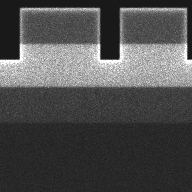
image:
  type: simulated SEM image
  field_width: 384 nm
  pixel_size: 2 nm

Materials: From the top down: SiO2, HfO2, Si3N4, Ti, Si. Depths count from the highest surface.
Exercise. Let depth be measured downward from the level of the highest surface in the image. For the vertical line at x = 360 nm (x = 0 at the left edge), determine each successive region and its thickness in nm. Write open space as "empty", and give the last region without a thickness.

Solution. SiO2 72, HfO2 86, Si3N4 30, Ti 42, Si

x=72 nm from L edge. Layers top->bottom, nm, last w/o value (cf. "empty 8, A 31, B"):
SiO2 72, HfO2 86, Si3N4 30, Ti 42, Si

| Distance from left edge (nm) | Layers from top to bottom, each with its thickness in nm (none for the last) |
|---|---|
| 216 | empty 104, HfO2 54, Si3N4 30, Ti 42, Si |